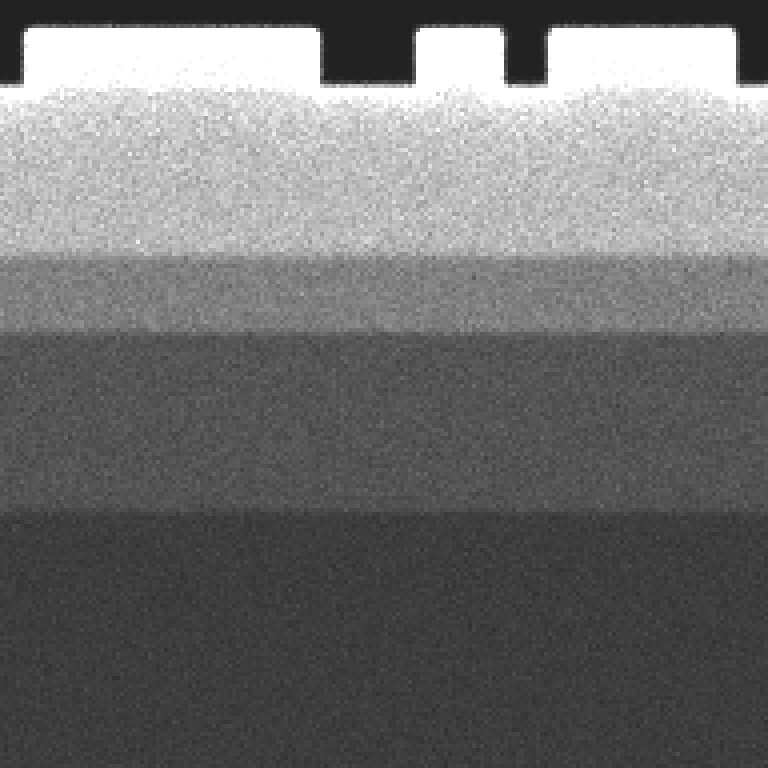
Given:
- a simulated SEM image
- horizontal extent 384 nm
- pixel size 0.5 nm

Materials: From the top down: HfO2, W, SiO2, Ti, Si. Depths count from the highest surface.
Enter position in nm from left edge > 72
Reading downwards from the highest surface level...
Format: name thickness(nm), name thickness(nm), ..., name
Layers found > HfO2 28, W 84, SiO2 38, Ti 90, Si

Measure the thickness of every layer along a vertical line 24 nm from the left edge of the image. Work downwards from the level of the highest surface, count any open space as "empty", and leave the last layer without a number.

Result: HfO2 28, W 84, SiO2 38, Ti 90, Si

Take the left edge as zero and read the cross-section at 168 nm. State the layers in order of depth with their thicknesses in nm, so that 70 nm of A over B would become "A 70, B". empty 28, W 84, SiO2 38, Ti 90, Si